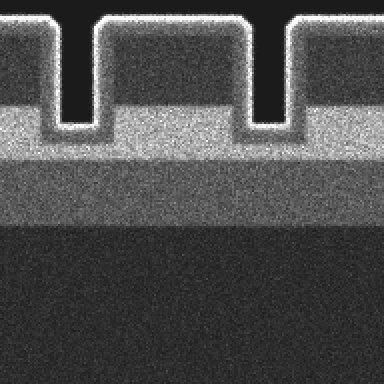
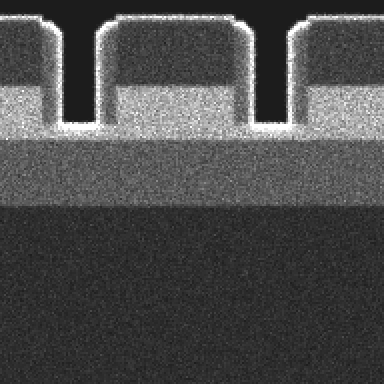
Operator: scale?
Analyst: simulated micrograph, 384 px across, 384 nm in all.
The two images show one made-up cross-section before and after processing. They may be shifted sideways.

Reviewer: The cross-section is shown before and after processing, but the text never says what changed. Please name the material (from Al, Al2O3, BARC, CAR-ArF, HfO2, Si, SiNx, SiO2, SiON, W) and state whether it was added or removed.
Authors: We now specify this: Al2O3, removed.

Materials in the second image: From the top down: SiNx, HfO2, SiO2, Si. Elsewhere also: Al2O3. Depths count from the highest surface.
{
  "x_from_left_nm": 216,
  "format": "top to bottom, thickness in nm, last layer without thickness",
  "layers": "SiNx 70, HfO2 54, SiO2 66, Si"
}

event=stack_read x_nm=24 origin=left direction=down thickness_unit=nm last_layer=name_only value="SiNx 70, HfO2 54, SiO2 66, Si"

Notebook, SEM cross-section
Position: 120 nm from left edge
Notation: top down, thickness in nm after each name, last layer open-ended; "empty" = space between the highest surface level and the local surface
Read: SiNx 70, HfO2 54, SiO2 66, Si